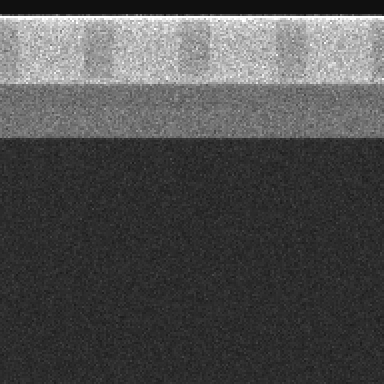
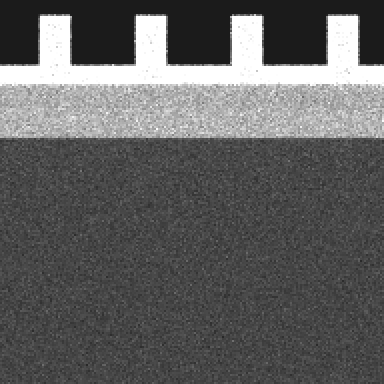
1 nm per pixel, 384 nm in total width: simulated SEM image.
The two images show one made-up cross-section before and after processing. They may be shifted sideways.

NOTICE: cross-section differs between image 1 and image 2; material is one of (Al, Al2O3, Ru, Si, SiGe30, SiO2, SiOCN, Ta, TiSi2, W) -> removed: W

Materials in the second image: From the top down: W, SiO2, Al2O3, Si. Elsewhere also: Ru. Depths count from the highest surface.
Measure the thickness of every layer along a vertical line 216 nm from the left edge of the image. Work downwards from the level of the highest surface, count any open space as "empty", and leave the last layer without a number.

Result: empty 50, W 18, SiO2 24, Al2O3 30, Si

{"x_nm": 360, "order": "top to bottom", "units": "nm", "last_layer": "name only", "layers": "empty 50, W 18, SiO2 24, Al2O3 30, Si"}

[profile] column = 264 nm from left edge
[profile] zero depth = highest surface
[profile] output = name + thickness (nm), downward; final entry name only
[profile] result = empty 50, W 18, SiO2 24, Al2O3 30, Si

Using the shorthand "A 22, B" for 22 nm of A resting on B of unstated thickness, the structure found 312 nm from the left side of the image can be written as empty 50, W 18, SiO2 24, Al2O3 30, Si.